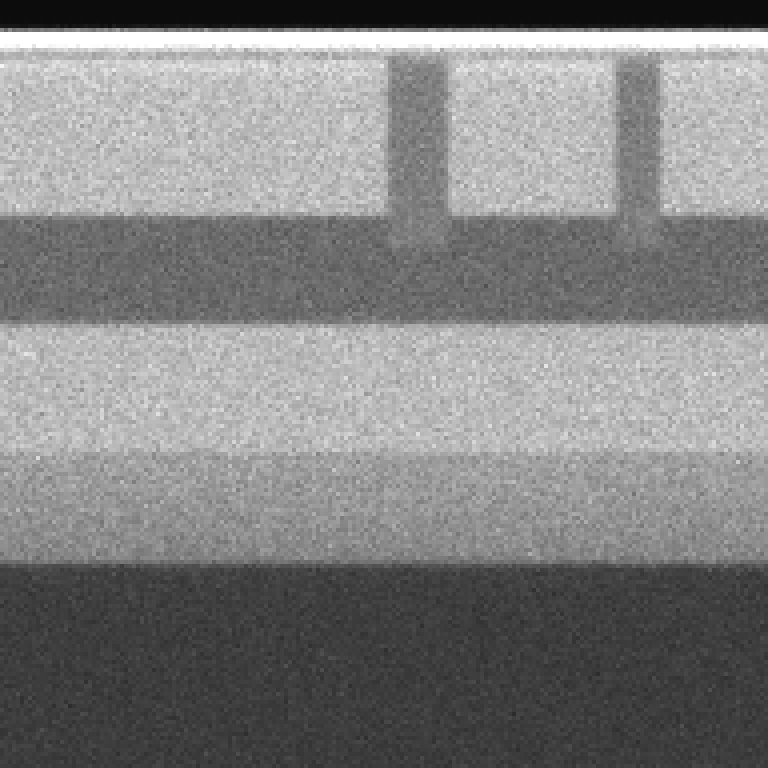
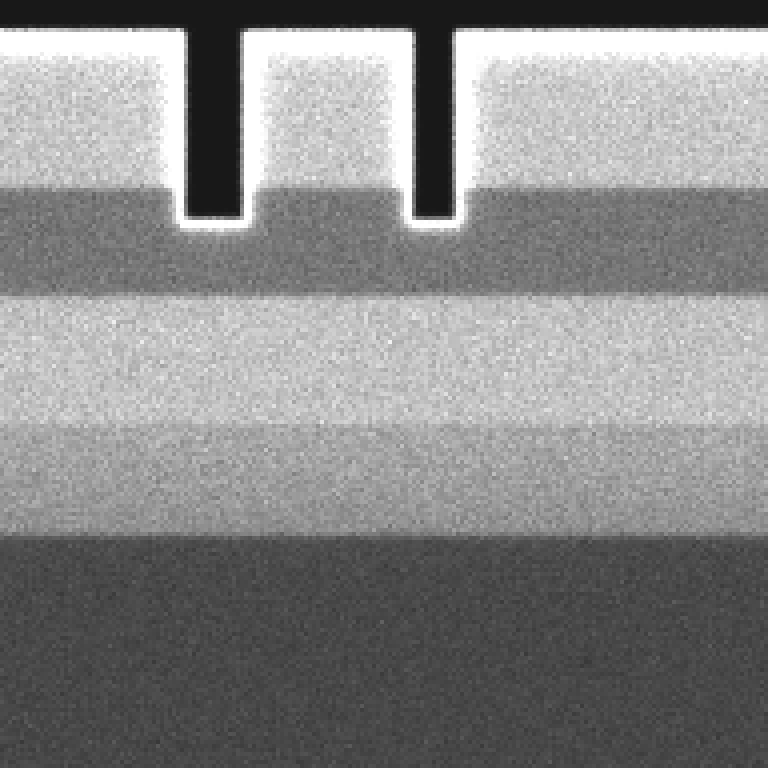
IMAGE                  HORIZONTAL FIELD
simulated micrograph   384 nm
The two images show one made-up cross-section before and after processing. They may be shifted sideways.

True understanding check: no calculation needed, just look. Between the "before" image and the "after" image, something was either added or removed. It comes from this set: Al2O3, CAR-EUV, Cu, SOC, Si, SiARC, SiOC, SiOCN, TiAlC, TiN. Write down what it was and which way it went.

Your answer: SOC (removed)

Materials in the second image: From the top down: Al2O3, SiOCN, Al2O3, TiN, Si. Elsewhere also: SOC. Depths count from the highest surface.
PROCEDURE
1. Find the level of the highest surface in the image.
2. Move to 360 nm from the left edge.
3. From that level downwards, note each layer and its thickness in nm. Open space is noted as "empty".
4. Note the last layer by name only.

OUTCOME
Al2O3 78, SiOCN 54, Al2O3 64, TiN 56, Si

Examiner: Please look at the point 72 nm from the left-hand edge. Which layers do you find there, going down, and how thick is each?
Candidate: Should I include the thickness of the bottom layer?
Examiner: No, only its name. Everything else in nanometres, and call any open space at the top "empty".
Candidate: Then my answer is Al2O3 78, SiOCN 54, Al2O3 64, TiN 56, Si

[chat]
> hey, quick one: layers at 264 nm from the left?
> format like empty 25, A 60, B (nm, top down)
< Al2O3 78, SiOCN 54, Al2O3 64, TiN 56, Si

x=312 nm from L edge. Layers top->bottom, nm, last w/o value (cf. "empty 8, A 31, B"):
Al2O3 78, SiOCN 54, Al2O3 64, TiN 56, Si